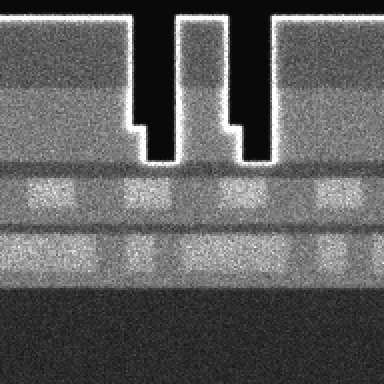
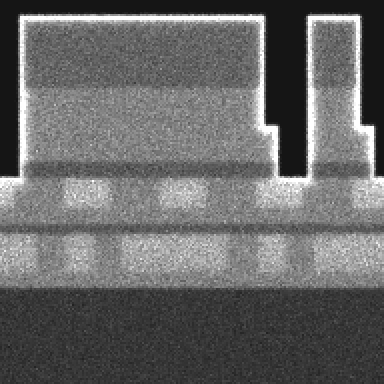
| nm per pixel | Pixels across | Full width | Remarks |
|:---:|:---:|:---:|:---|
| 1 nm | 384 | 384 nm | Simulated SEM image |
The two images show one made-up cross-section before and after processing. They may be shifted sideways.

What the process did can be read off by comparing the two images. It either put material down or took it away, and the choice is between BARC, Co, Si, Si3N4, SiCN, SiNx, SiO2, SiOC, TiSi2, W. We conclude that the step removed SiNx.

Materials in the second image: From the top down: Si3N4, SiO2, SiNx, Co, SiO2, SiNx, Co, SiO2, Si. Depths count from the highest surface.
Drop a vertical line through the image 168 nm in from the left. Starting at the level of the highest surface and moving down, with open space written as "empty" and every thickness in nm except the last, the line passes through Si3N4 72, SiO2 74, SiNx 16, Co 30, SiO2 16, SiNx 10, Co 38, SiO2 16, Si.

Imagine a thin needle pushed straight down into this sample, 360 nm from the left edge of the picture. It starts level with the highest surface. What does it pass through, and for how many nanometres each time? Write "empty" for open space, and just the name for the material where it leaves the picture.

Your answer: empty 110, SiO2 36, SiNx 16, Co 30, SiO2 16, SiNx 10, Co 38, SiO2 16, Si